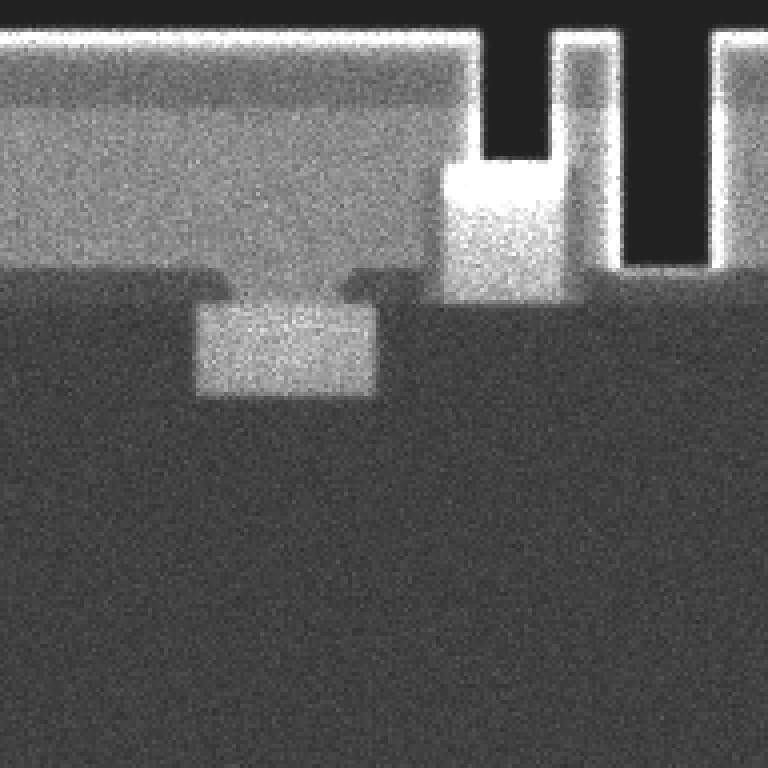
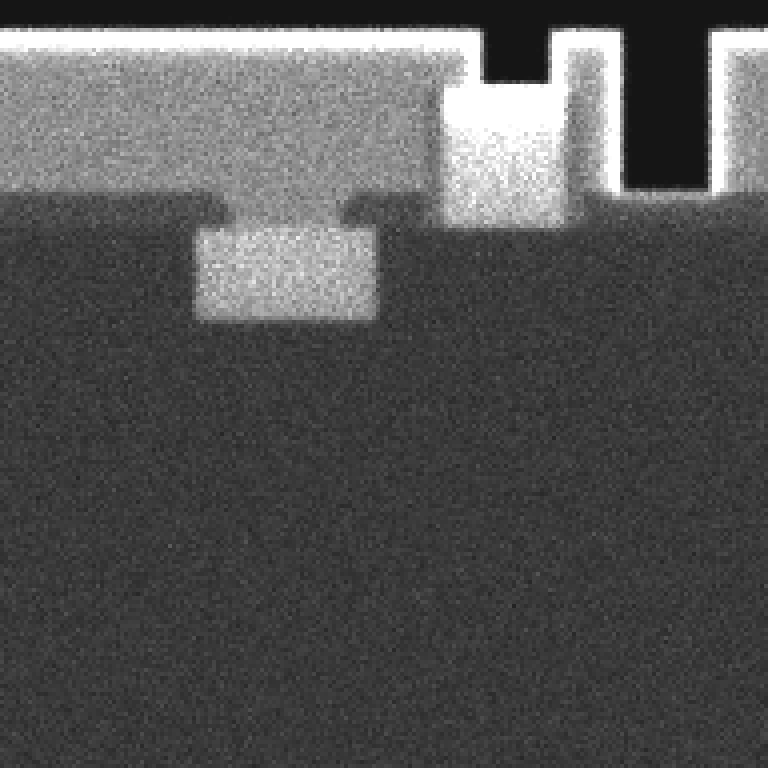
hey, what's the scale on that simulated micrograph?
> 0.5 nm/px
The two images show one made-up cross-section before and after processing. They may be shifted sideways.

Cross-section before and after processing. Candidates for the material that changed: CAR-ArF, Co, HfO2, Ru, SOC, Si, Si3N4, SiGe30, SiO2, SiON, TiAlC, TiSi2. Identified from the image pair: SOC (removed).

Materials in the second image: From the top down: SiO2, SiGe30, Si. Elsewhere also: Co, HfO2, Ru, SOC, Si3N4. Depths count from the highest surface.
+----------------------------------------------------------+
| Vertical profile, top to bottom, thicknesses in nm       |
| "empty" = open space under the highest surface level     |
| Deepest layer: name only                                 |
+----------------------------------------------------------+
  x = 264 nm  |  empty 28, HfO2 18, Ru 52, Si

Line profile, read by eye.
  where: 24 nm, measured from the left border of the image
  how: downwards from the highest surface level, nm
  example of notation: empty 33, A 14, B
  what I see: SiO2 80, SiGe30 18, Si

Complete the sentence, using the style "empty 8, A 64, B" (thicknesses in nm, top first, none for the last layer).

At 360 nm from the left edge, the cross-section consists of SiO2 80, SiGe30 18, Si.